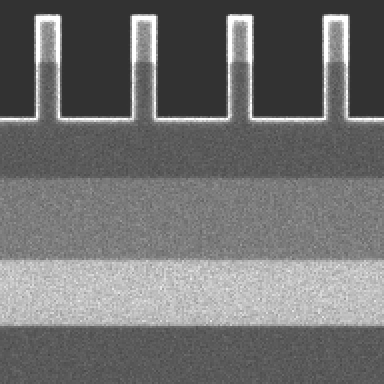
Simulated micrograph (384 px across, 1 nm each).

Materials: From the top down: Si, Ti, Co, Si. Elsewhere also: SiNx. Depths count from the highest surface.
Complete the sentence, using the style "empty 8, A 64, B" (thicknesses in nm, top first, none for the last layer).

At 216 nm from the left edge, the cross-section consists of empty 102, Si 60, Ti 82, Co 66, Si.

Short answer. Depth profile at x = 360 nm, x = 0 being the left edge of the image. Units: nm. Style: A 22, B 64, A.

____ empty 102, Si 60, Ti 82, Co 66, Si